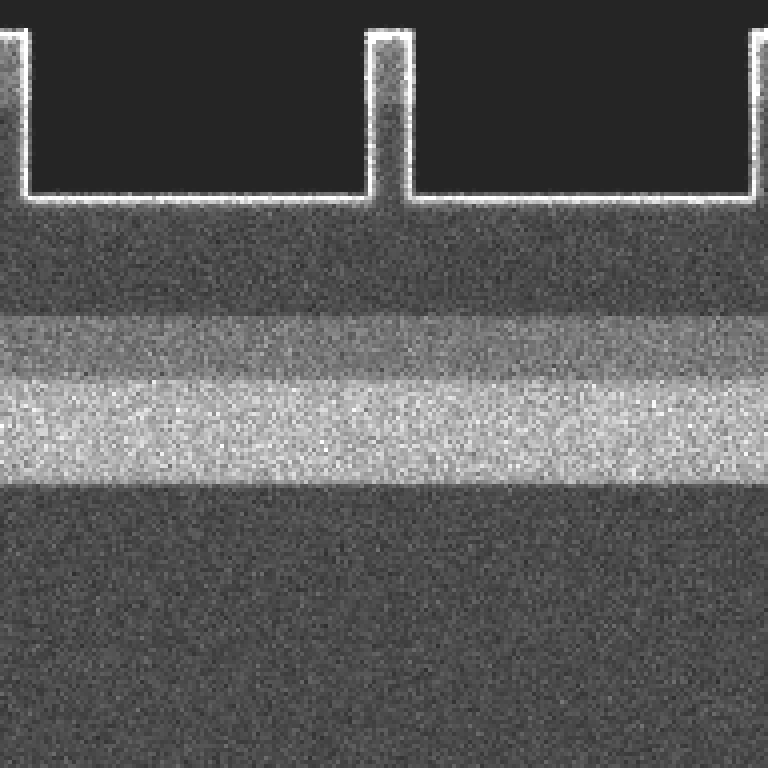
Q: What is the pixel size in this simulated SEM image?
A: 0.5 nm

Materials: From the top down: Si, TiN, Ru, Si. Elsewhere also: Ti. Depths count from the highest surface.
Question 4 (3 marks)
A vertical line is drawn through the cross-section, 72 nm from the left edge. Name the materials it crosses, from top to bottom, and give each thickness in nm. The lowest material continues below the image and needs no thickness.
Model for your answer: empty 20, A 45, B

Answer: empty 82, Si 60, TiN 32, Ru 52, Si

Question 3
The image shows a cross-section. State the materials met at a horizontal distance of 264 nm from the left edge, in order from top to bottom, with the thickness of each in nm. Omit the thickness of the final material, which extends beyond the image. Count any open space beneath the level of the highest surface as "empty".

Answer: empty 82, Si 60, TiN 32, Ru 52, Si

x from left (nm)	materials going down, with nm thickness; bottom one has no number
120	empty 82, Si 60, TiN 32, Ru 52, Si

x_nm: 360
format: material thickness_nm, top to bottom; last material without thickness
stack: empty 82, Si 60, TiN 32, Ru 52, Si